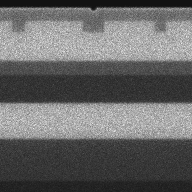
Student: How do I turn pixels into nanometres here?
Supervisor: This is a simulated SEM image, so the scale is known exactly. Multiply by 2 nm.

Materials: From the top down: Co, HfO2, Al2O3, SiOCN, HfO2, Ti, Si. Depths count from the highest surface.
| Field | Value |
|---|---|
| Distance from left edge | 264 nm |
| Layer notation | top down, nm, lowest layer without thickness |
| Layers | Co 26, HfO2 80, Al2O3 28, SiOCN 56, HfO2 72, Ti 84, Si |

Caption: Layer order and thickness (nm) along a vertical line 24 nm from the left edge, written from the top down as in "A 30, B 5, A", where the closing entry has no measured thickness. Co 48, HfO2 58, Al2O3 28, SiOCN 56, HfO2 72, Ti 84, Si